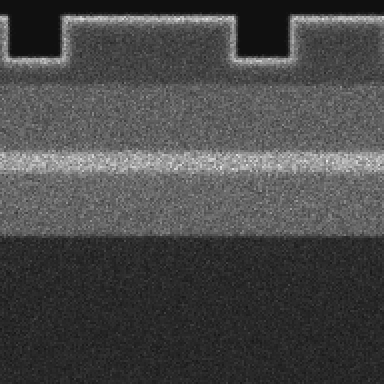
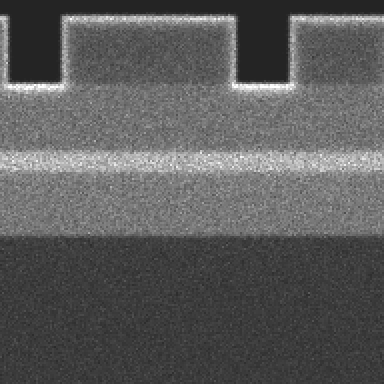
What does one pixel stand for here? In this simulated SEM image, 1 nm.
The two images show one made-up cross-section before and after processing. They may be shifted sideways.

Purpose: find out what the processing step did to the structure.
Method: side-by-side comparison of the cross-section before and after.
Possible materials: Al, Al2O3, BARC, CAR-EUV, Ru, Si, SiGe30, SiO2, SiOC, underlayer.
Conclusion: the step removed underlayer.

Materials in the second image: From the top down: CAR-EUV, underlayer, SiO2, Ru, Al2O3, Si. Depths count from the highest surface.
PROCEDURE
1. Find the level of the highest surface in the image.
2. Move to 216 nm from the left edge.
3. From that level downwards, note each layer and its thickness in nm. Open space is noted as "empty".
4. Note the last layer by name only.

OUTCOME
CAR-EUV 42, underlayer 26, SiO2 68, Ru 20, Al2O3 64, Si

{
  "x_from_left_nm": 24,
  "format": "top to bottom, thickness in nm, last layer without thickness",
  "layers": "empty 68, SiO2 68, Ru 20, Al2O3 64, Si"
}